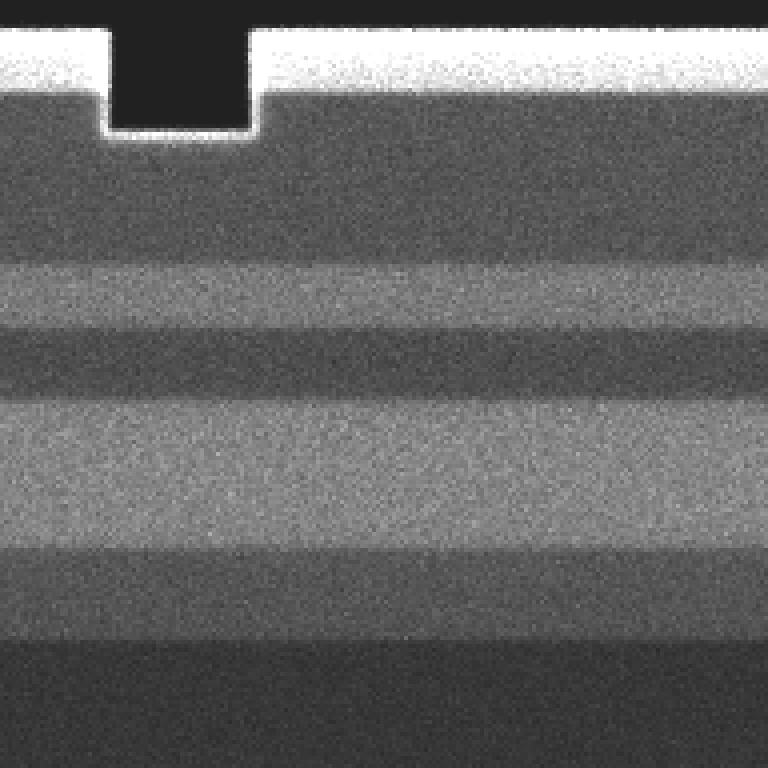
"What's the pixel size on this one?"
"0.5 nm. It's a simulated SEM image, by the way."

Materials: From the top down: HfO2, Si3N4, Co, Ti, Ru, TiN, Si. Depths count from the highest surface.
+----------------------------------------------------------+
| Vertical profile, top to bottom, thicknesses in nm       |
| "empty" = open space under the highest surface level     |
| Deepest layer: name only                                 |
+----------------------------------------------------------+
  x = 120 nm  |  empty 50, Si3N4 66, Co 32, Ti 36, Ru 74, TiN 46, Si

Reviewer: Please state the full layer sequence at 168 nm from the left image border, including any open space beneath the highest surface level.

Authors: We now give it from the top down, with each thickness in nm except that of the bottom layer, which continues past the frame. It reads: HfO2 30, Si3N4 86, Co 32, Ti 36, Ru 74, TiN 46, Si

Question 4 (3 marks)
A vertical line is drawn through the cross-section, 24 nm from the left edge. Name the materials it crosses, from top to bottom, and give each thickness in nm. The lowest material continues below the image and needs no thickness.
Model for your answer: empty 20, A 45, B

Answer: HfO2 30, Si3N4 86, Co 32, Ti 36, Ru 74, TiN 46, Si